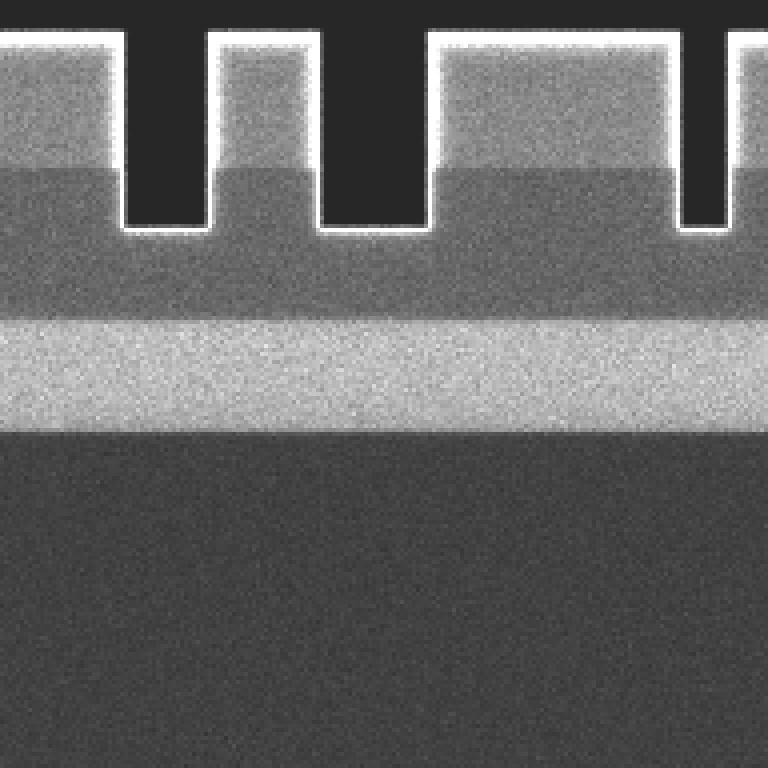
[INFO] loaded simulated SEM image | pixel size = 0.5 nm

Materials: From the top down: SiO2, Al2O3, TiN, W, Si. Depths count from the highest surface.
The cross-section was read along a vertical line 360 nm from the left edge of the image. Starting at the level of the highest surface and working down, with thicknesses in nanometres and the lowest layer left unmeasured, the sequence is empty 98, TiN 46, W 56, Si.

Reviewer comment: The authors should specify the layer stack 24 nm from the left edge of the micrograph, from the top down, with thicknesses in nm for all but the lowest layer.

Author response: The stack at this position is SiO2 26, Al2O3 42, TiN 76, W 56, Si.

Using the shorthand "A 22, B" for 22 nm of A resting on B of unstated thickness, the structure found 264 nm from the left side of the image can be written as SiO2 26, Al2O3 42, TiN 76, W 56, Si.